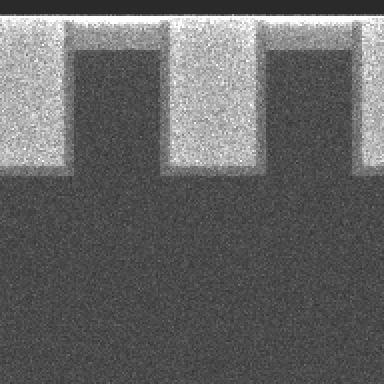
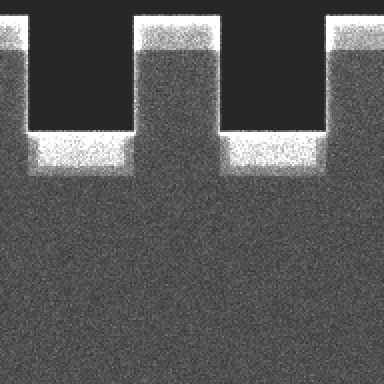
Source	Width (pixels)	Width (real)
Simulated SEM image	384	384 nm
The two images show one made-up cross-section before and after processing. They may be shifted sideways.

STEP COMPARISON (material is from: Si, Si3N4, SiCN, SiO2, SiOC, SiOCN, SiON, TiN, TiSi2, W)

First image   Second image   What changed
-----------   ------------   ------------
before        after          Si3N4 and W, removed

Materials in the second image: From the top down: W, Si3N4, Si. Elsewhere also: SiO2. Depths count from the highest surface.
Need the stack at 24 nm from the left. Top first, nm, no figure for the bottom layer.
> SiO2 34, Si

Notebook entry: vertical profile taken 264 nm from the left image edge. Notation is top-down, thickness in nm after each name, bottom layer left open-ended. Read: empty 116, W 34, Si3N4 10, Si